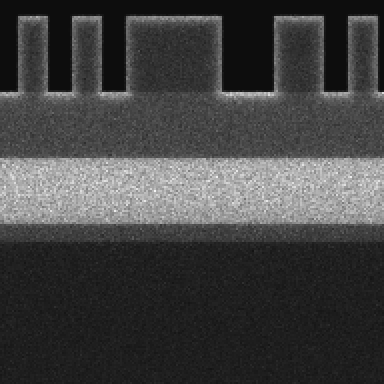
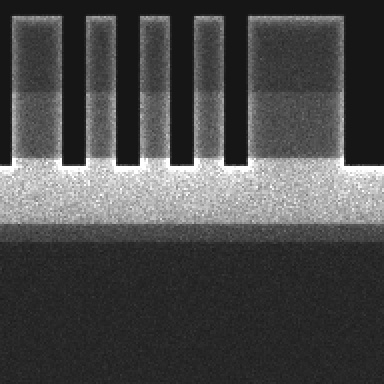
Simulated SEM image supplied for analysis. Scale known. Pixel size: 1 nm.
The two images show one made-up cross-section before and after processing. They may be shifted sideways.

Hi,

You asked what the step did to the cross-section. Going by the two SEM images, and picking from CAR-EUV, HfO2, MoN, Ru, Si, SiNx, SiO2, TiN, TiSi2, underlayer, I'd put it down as HfO2 and SiO2, removed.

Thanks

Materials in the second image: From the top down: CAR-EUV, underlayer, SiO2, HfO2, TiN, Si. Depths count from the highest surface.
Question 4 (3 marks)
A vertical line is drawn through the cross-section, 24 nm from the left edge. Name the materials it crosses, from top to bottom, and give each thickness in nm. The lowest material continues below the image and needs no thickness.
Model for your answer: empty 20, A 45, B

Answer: CAR-EUV 40, underlayer 36, SiO2 66, HfO2 66, TiN 18, Si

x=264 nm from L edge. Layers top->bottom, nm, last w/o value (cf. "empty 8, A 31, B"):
CAR-EUV 40, underlayer 36, SiO2 66, HfO2 66, TiN 18, Si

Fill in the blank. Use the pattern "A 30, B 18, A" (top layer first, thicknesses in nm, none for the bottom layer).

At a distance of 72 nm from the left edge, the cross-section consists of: empty 150, HfO2 58, TiN 18, Si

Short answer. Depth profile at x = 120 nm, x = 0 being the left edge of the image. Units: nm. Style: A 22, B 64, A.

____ empty 150, HfO2 58, TiN 18, Si